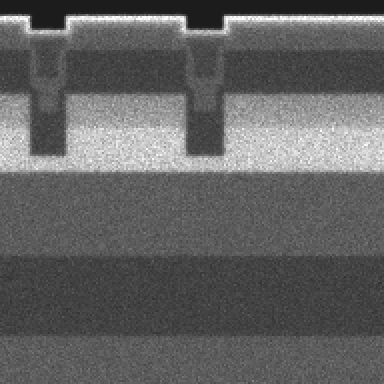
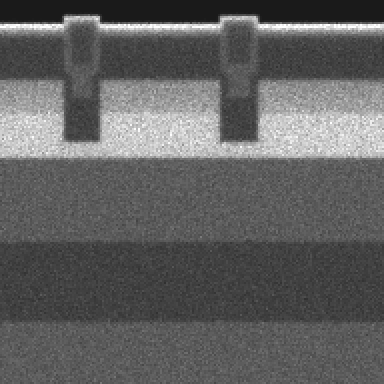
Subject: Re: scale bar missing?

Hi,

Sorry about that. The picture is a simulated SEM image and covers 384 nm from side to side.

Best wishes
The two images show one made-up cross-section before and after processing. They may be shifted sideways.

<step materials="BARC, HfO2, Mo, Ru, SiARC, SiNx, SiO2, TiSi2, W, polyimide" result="removed SiO2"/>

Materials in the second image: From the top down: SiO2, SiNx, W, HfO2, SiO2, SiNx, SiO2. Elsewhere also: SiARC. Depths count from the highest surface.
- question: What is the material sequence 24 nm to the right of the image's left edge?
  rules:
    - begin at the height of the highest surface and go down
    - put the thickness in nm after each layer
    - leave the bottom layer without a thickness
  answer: empty 8, SiO2 12, SiNx 44, W 34, HfO2 44, SiO2 84, SiNx 80, SiO2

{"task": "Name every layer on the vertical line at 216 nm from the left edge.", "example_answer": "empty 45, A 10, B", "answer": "empty 8, SiO2 12, SiNx 44, W 34, HfO2 44, SiO2 84, SiNx 80, SiO2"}